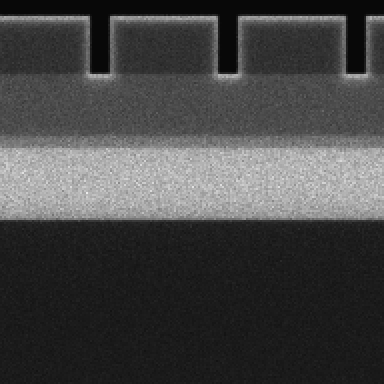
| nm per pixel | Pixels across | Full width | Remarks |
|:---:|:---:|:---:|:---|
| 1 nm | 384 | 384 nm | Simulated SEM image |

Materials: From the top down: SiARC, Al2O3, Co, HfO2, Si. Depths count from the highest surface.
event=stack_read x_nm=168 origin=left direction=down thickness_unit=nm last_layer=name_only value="SiARC 58, Al2O3 62, Co 12, HfO2 72, Si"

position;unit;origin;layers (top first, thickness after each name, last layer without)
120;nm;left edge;SiARC 58, Al2O3 62, Co 12, HfO2 72, Si